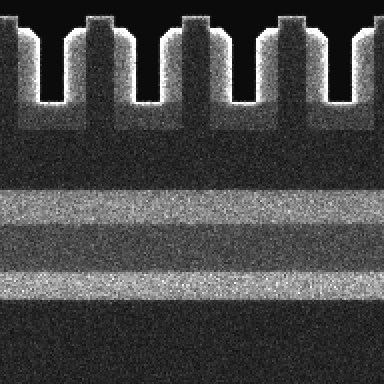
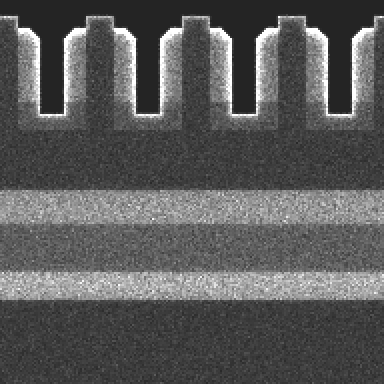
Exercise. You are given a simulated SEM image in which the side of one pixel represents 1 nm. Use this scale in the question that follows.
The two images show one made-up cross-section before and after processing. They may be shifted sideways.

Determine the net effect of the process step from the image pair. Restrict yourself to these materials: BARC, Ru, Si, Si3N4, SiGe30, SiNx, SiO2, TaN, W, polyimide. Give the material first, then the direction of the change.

SiNx: removed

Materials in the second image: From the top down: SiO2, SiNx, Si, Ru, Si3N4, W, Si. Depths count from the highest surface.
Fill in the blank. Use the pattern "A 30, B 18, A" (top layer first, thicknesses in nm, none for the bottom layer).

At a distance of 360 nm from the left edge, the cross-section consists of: empty 14, SiO2 72, SiNx 28, Si 60, Ru 34, Si3N4 48, W 28, Si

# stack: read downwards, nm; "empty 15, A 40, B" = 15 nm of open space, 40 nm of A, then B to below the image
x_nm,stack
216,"empty 12, SiO2 74, SiNx 28, Si 60, Ru 34, Si3N4 48, W 28, Si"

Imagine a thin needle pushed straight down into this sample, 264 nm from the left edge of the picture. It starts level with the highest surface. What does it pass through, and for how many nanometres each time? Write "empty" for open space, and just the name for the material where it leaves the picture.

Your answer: empty 14, SiO2 72, SiNx 28, Si 60, Ru 34, Si3N4 48, W 28, Si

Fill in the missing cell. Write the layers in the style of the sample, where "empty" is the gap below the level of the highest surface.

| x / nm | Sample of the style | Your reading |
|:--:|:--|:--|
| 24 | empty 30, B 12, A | empty 12, SiO2 74, SiNx 28, Si 60, Ru 34, Si3N4 48, W 28, Si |